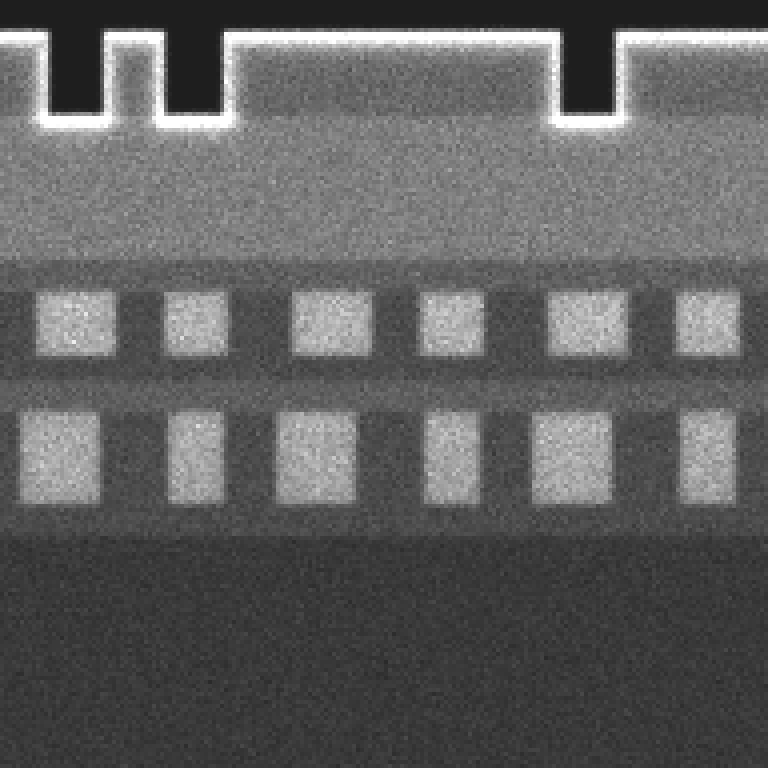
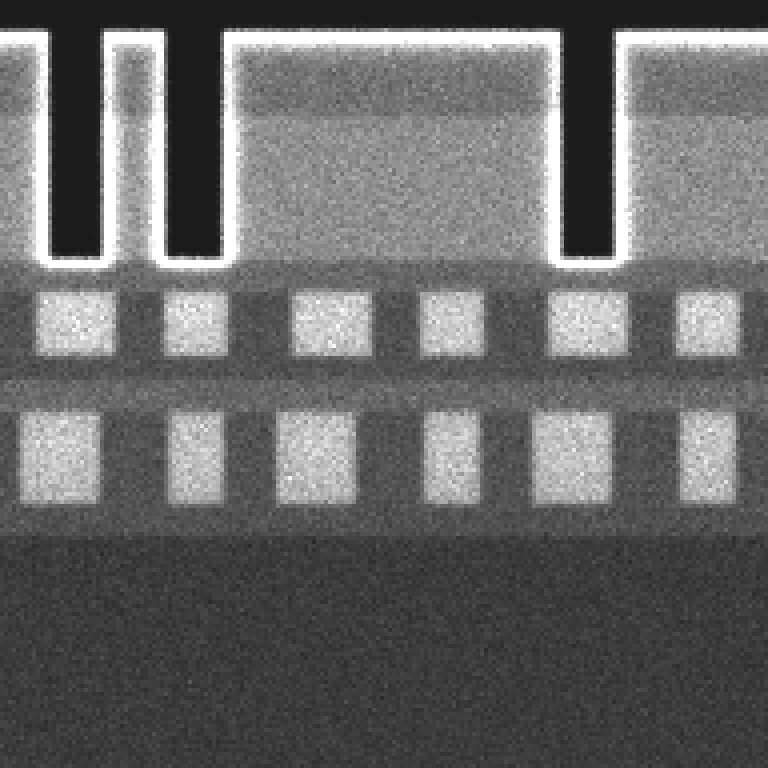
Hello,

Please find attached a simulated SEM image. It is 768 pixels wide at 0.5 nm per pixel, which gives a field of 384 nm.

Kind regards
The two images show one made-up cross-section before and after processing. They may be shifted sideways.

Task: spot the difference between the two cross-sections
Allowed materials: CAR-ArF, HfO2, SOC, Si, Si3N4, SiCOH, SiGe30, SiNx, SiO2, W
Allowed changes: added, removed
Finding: removed SiO2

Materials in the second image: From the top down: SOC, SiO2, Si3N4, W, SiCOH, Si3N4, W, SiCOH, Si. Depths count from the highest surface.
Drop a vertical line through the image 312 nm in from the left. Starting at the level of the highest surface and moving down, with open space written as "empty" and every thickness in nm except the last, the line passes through SOC 42, SiO2 72, Si3N4 16, W 32, SiCOH 12, Si3N4 16, SiCOH 62, Si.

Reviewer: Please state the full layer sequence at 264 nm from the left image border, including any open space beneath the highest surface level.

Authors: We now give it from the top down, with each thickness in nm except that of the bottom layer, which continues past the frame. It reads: SOC 42, SiO2 72, Si3N4 16, SiCOH 44, Si3N4 16, SiCOH 62, Si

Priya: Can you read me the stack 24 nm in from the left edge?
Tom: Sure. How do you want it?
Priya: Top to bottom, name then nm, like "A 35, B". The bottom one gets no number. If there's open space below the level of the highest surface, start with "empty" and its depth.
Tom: empty 114, Si3N4 16, W 32, SiCOH 12, Si3N4 16, W 46, SiCOH 16, Si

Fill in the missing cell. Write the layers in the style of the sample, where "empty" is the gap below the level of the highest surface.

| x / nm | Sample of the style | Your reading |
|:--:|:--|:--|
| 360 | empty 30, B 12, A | SOC 42, SiO2 72, Si3N4 16, W 32, SiCOH 12, Si3N4 16, W 46, SiCOH 16, Si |